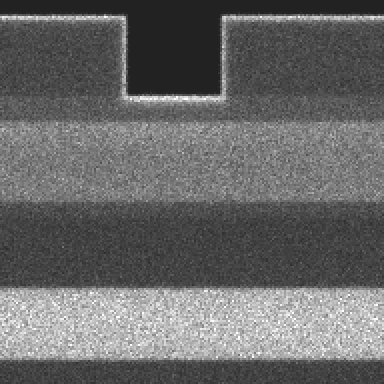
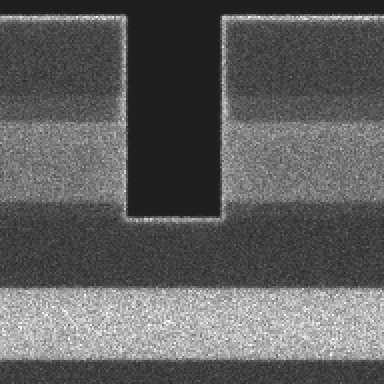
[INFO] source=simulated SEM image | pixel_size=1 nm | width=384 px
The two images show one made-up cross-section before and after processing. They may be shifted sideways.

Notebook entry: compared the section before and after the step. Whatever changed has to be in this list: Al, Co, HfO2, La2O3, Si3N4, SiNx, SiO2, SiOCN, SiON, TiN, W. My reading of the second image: SiO2 and TiN and W removed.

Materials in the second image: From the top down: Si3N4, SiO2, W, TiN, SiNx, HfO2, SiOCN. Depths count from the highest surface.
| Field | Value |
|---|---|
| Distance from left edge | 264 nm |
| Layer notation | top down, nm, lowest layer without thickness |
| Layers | Si3N4 80, SiO2 26, W 80, TiN 16, SiNx 70, HfO2 72, SiOCN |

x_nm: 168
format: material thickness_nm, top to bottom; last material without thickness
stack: empty 202, SiNx 70, HfO2 72, SiOCN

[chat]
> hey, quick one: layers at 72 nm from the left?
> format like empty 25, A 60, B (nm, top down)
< Si3N4 80, SiO2 26, W 80, TiN 16, SiNx 70, HfO2 72, SiOCN